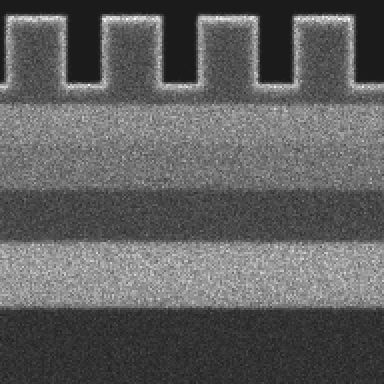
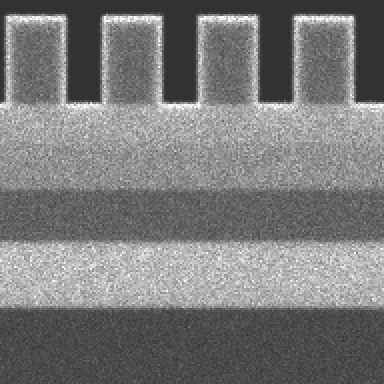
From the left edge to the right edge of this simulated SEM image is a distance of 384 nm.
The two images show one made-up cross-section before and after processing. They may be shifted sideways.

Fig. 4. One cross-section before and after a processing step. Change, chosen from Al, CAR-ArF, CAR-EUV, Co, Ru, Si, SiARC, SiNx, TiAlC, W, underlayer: underlayer removed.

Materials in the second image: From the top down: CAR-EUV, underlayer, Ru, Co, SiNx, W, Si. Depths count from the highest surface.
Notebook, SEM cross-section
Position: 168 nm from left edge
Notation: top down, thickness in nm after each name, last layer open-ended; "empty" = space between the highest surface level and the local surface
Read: empty 88, Ru 40, Co 46, SiNx 52, W 66, Si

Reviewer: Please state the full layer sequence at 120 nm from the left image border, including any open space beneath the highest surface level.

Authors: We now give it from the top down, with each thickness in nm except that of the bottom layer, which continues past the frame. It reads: CAR-EUV 68, underlayer 20, Ru 40, Co 46, SiNx 52, W 66, Si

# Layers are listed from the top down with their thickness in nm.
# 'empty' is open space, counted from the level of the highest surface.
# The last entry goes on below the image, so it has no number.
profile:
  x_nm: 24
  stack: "CAR-EUV 68, underlayer 20, Ru 40, Co 46, SiNx 52, W 66, Si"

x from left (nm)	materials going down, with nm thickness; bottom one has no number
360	empty 88, Ru 40, Co 46, SiNx 52, W 66, Si